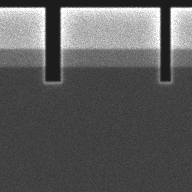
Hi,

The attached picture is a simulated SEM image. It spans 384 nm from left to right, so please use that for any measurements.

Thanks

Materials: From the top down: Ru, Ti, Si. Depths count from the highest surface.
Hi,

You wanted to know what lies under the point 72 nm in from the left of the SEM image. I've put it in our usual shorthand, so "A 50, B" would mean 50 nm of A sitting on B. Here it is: Ru 82, Ti 36, Si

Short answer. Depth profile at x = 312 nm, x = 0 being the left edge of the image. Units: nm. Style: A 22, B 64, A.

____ Ru 82, Ti 36, Si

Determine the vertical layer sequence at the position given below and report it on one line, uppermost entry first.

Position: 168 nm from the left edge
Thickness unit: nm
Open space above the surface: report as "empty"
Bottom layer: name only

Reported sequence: Ru 82, Ti 36, Si